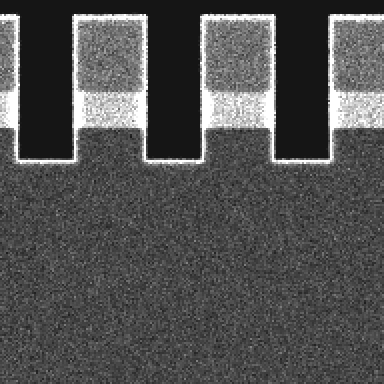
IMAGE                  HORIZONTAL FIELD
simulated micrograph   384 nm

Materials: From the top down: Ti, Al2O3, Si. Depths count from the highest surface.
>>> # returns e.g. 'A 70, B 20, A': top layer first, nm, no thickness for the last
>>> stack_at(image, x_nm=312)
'empty 144, Si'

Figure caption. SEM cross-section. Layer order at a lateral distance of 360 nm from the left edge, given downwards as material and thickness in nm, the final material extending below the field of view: Ti 76, Al2O3 36, Si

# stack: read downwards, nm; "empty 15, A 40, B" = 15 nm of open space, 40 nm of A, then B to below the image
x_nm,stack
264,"Ti 76, Al2O3 36, Si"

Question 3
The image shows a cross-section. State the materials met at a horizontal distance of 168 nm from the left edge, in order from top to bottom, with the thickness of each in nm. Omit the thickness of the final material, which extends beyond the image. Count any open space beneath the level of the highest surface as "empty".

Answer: empty 144, Si